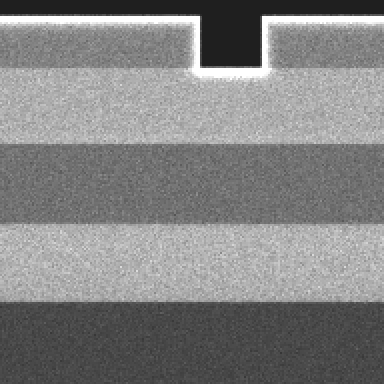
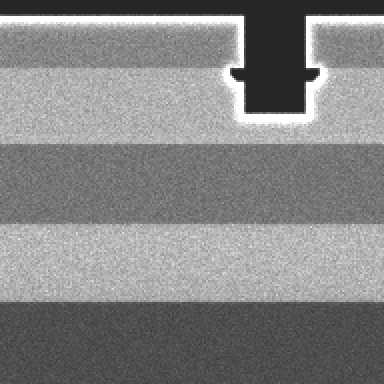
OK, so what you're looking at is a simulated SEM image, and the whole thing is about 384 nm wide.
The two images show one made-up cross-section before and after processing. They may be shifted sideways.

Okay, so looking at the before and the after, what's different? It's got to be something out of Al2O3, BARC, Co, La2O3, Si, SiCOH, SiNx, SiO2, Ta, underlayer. SiO2, removed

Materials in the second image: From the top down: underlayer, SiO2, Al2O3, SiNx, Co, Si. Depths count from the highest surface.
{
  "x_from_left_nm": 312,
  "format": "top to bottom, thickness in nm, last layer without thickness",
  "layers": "underlayer 52, empty 14, SiO2 52, Al2O3 10, SiNx 80, Co 78, Si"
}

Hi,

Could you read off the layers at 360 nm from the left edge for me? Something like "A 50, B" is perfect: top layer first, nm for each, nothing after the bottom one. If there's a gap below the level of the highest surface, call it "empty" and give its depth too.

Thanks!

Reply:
underlayer 52, SiO2 66, Al2O3 10, SiNx 80, Co 78, Si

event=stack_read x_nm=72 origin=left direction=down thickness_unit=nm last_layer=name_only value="underlayer 52, SiO2 66, Al2O3 10, SiNx 80, Co 78, Si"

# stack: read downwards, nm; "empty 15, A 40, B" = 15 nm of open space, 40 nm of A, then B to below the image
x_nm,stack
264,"empty 98, SiO2 20, Al2O3 10, SiNx 80, Co 78, Si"